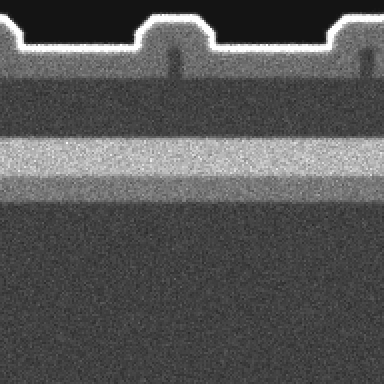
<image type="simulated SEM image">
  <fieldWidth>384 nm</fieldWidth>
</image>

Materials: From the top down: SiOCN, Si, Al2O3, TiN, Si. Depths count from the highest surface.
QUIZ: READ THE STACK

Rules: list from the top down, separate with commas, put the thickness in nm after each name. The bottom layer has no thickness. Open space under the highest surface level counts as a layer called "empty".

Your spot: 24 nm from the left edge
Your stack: empty 30, SiOCN 32, Si 60, Al2O3 38, TiN 26, Si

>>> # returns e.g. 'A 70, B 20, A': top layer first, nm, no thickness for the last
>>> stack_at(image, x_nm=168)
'SiOCN 32, Si 90, Al2O3 38, TiN 26, Si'